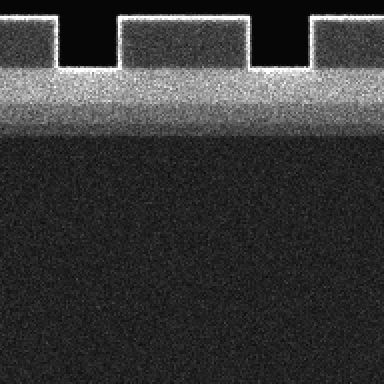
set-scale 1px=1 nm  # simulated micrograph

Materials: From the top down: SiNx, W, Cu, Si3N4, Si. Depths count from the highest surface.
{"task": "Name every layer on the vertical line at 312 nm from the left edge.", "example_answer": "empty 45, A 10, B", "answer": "SiNx 52, W 36, Cu 20, Si3N4 12, Si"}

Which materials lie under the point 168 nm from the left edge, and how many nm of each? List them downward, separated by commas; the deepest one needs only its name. SiNx 52, W 36, Cu 20, Si3N4 12, Si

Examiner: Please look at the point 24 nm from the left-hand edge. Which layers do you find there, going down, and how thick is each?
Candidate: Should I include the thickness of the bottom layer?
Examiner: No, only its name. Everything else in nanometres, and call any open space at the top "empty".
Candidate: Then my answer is SiNx 52, W 36, Cu 20, Si3N4 12, Si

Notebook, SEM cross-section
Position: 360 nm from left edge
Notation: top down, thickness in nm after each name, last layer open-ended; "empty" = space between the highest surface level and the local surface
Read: SiNx 52, W 36, Cu 20, Si3N4 12, Si